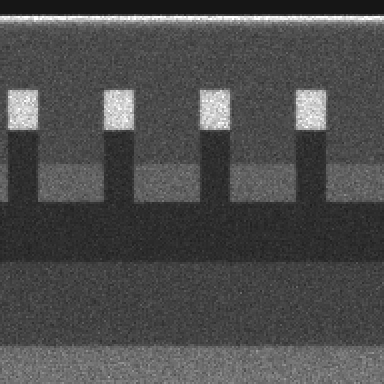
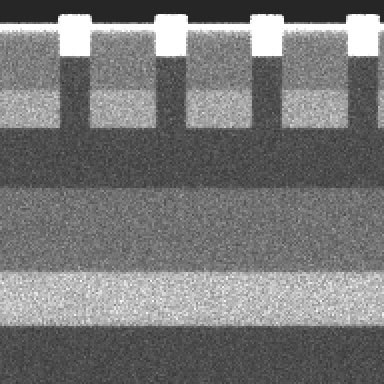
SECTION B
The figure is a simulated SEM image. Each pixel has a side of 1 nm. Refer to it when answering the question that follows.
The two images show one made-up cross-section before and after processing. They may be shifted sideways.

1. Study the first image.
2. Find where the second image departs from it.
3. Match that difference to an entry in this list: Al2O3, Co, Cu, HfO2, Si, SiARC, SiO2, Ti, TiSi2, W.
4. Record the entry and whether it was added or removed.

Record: SiARC / removed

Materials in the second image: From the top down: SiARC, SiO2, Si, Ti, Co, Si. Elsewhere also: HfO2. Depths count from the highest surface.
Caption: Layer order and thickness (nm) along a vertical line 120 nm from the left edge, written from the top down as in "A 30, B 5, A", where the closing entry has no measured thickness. empty 8, SiARC 66, SiO2 38, Si 60, Ti 84, Co 54, Si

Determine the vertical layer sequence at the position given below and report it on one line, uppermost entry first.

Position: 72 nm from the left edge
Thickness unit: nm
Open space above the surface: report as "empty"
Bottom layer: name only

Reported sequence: HfO2 40, Si 132, Ti 84, Co 54, Si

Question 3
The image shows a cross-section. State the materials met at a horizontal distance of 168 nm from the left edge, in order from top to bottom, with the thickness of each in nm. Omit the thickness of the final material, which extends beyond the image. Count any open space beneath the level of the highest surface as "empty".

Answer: HfO2 40, Si 132, Ti 84, Co 54, Si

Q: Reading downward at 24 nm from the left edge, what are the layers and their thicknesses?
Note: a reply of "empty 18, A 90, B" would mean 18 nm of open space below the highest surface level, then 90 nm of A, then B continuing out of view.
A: empty 8, SiARC 66, SiO2 38, Si 60, Ti 84, Co 54, Si